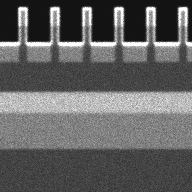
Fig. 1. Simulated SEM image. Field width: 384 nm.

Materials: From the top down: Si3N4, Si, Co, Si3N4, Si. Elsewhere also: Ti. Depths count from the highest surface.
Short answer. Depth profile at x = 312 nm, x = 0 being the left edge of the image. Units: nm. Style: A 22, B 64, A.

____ empty 70, Si3N4 38, Si 60, Co 42, Si3N4 72, Si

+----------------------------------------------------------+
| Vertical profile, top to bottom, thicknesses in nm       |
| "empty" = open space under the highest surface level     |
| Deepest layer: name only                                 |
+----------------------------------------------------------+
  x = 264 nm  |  empty 70, Si3N4 38, Si 60, Co 42, Si3N4 72, Si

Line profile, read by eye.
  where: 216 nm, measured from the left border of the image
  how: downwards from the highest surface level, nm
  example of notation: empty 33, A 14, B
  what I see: empty 70, Si3N4 38, Si 60, Co 42, Si3N4 72, Si